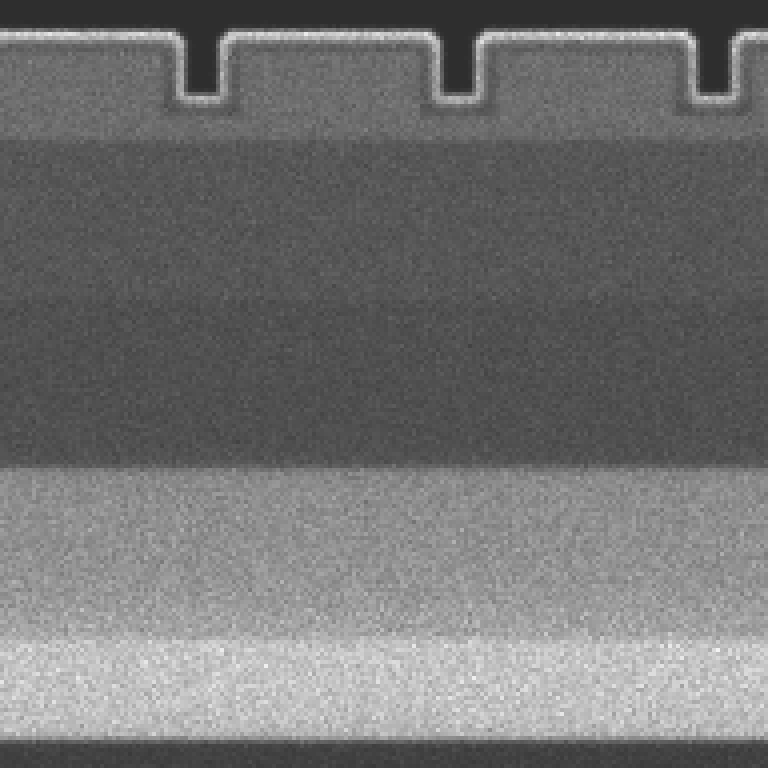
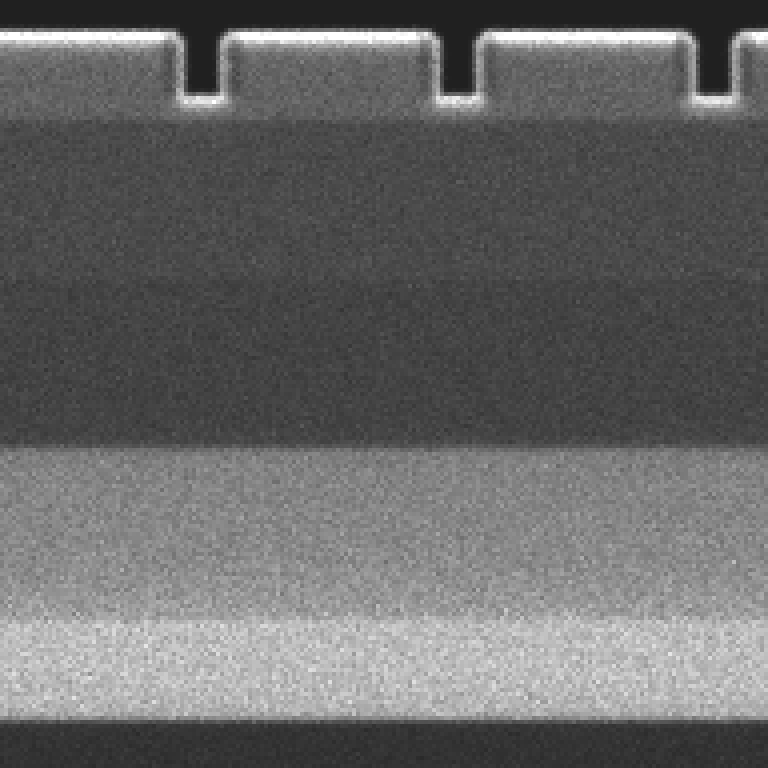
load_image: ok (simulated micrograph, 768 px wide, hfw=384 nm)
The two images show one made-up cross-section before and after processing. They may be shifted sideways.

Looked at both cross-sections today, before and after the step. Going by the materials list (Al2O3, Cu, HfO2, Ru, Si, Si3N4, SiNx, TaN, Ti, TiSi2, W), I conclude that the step removed SiNx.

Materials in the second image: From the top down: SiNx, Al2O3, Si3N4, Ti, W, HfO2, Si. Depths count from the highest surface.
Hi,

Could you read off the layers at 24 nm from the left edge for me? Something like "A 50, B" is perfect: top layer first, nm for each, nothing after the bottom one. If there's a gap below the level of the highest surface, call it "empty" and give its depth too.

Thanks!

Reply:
Al2O3 44, Si3N4 80, Ti 84, W 86, HfO2 50, Si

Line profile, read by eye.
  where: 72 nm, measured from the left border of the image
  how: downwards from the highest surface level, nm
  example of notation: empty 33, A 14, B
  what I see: Al2O3 44, Si3N4 80, Ti 84, W 86, HfO2 50, Si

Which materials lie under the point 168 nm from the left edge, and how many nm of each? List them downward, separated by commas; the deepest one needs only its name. Al2O3 44, Si3N4 80, Ti 84, W 86, HfO2 50, Si